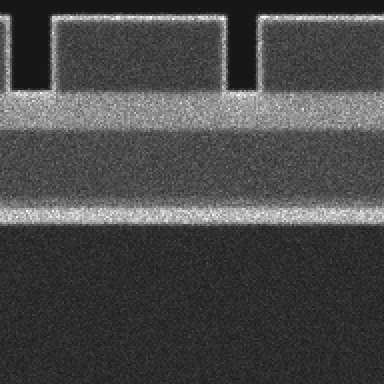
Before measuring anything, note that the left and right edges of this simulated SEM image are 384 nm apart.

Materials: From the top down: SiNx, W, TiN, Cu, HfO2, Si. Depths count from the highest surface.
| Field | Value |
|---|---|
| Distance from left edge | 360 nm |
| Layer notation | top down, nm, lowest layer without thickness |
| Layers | SiNx 76, W 38, TiN 68, Cu 10, HfO2 16, Si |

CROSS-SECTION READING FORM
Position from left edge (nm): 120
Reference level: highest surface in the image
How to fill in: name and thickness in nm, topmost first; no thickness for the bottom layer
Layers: SiNx 76, W 38, TiN 68, Cu 10, HfO2 16, Si